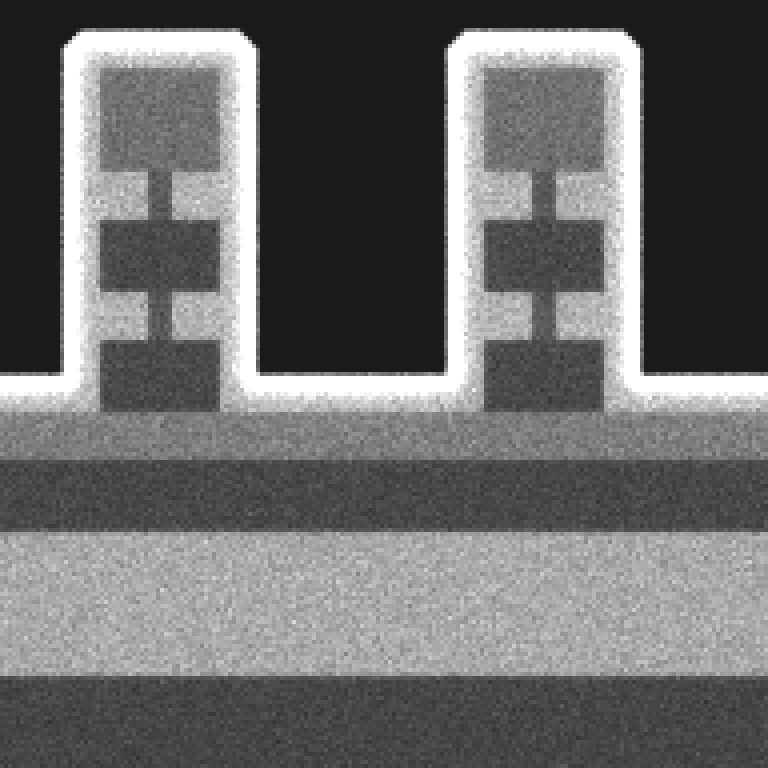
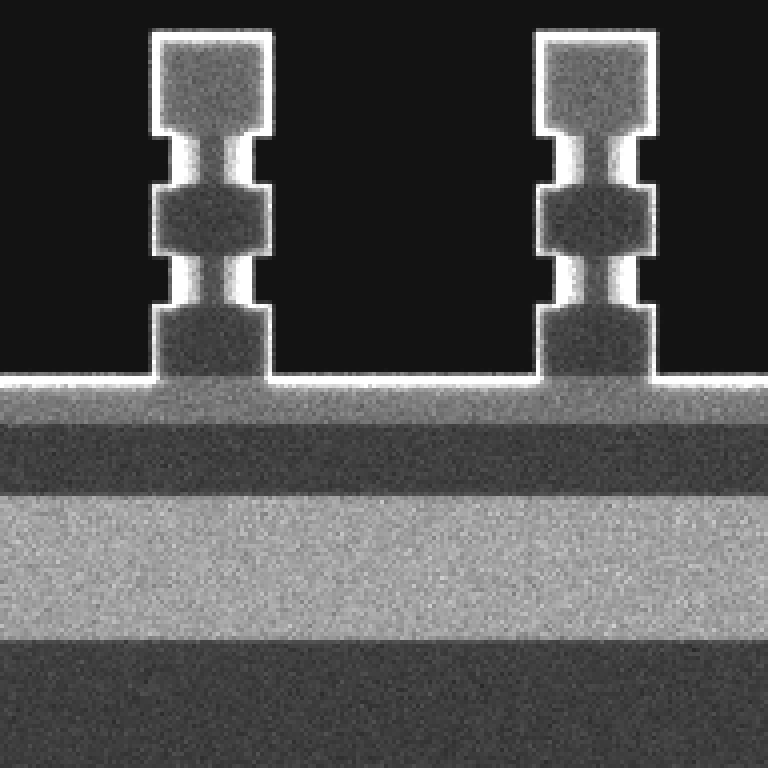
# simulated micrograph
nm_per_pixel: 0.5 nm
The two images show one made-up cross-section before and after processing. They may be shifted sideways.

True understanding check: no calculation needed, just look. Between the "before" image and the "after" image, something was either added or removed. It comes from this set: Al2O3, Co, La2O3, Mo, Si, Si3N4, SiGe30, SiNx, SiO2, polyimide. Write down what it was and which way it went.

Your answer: Al2O3 (removed)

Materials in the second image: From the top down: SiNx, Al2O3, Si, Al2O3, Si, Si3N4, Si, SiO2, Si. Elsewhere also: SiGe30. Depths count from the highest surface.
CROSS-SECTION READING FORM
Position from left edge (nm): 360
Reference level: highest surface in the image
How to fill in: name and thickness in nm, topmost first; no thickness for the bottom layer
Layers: empty 172, Si3N4 24, Si 36, SiO2 72, Si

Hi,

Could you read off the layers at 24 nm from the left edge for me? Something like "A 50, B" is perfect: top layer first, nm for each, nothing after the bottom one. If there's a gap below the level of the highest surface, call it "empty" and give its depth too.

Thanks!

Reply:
empty 172, Si3N4 24, Si 36, SiO2 72, Si